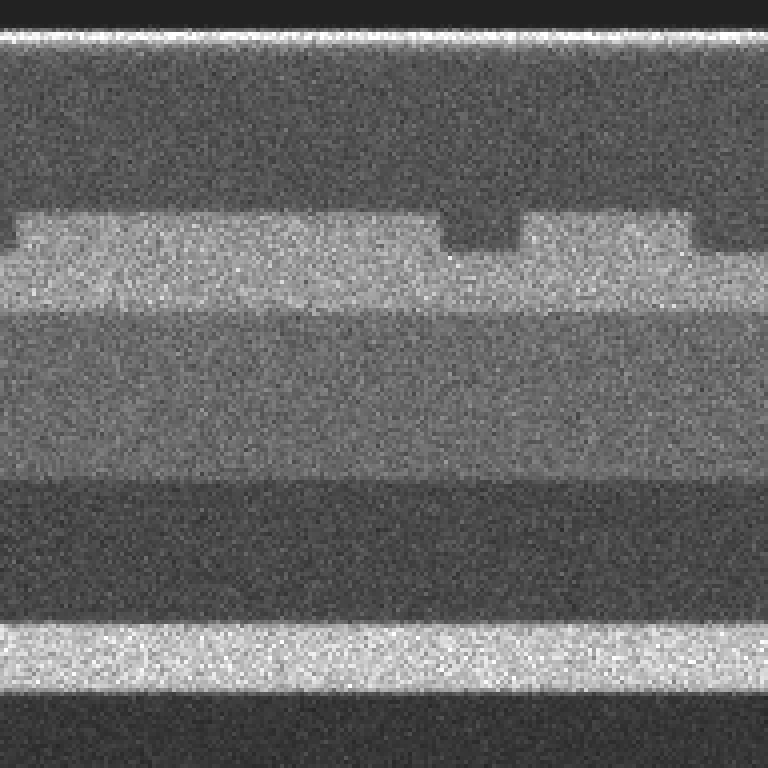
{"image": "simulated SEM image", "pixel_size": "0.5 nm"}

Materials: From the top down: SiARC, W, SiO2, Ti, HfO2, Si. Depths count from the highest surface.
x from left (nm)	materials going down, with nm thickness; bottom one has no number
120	SiARC 90, W 50, SiO2 84, Ti 72, HfO2 34, Si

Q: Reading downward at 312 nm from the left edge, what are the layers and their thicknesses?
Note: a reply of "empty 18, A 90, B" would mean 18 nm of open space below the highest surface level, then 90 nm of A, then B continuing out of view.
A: SiARC 90, W 50, SiO2 84, Ti 72, HfO2 34, Si